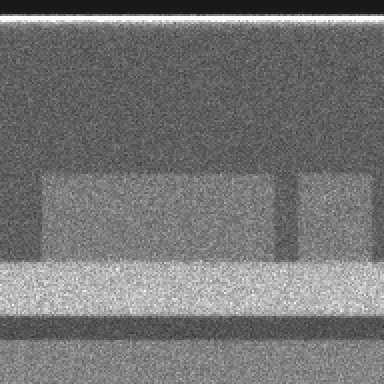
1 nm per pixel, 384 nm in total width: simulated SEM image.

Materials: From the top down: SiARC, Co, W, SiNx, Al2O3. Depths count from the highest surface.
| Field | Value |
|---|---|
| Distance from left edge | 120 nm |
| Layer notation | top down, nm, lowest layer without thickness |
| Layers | SiARC 158, Co 88, W 54, SiNx 24, Al2O3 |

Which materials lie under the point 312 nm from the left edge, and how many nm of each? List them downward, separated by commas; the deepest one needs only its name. SiARC 158, Co 88, W 54, SiNx 24, Al2O3